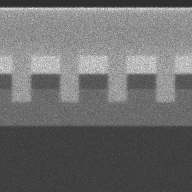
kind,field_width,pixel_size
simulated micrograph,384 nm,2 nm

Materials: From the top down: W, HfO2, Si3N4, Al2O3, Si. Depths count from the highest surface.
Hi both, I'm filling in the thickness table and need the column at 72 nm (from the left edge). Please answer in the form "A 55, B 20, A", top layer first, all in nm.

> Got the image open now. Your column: W 96, HfO2 36, Si3N4 30, Al2O3 74, Si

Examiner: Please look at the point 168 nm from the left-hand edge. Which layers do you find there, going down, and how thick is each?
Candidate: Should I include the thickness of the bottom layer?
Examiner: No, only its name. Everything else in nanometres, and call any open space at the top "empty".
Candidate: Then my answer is W 96, HfO2 36, Si3N4 30, Al2O3 74, Si